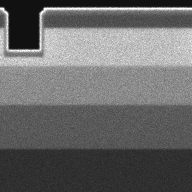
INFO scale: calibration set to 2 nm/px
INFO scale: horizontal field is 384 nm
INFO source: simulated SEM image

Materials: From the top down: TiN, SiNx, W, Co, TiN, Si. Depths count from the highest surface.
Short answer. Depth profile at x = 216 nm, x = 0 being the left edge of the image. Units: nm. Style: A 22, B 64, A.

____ TiN 14, SiNx 26, W 76, Co 78, TiN 88, Si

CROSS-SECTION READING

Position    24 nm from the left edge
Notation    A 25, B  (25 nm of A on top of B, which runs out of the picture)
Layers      empty 84, TiN 14, W 18, Co 78, TiN 88, Si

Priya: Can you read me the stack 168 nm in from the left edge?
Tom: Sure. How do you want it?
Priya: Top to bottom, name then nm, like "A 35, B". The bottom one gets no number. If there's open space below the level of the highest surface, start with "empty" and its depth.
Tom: TiN 14, SiNx 26, W 76, Co 78, TiN 88, Si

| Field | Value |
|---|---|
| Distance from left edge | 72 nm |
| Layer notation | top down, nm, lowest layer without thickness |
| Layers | empty 84, TiN 14, W 18, Co 78, TiN 88, Si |